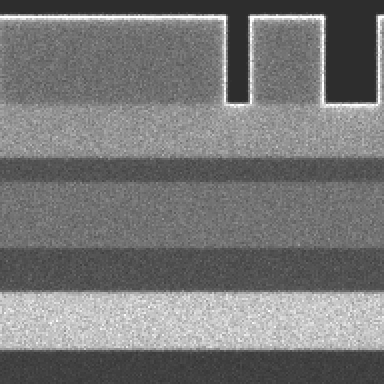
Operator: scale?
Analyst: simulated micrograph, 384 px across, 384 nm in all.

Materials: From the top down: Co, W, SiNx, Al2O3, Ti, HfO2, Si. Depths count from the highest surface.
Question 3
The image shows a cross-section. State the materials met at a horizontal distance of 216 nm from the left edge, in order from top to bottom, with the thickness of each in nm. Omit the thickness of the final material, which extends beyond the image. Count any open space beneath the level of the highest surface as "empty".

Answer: Co 88, W 54, SiNx 24, Al2O3 66, Ti 44, HfO2 58, Si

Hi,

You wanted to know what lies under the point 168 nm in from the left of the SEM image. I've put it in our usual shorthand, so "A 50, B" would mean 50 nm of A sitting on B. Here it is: Co 88, W 54, SiNx 24, Al2O3 66, Ti 44, HfO2 58, Si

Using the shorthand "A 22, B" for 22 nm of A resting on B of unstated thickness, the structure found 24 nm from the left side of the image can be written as Co 88, W 54, SiNx 24, Al2O3 66, Ti 44, HfO2 58, Si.